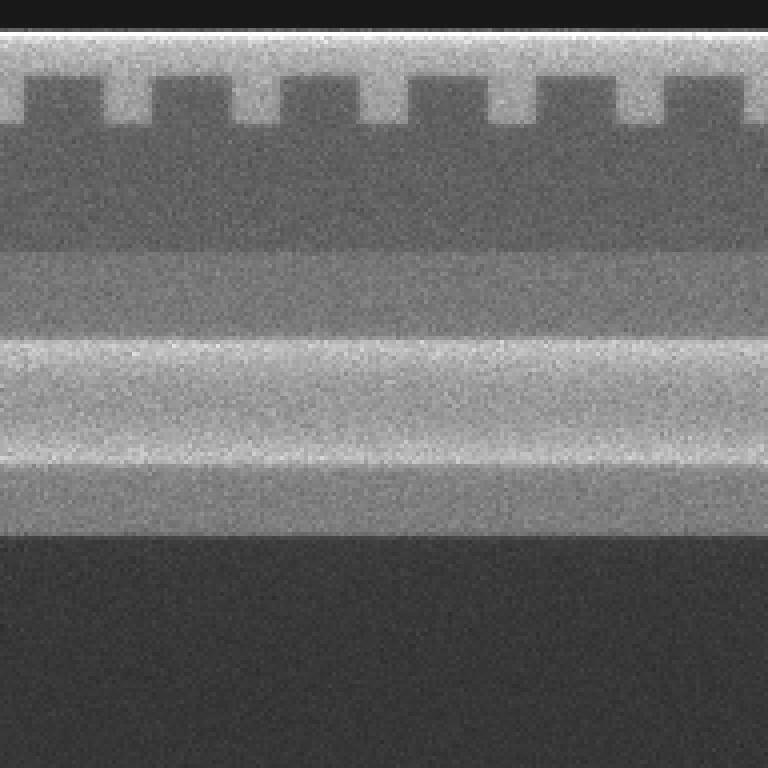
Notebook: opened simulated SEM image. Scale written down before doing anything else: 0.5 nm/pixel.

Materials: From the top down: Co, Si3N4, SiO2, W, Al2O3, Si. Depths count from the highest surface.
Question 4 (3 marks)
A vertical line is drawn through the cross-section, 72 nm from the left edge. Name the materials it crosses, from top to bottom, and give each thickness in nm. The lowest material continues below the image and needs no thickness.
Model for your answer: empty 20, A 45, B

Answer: Co 46, Si3N4 64, SiO2 44, W 62, Al2O3 36, Si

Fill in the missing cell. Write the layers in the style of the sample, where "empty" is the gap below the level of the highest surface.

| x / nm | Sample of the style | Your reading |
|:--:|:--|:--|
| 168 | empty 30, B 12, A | Co 22, Si3N4 88, SiO2 44, W 62, Al2O3 36, Si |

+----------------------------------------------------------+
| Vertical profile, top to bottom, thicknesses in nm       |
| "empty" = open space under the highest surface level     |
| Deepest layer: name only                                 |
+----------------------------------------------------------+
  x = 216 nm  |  Co 22, Si3N4 88, SiO2 44, W 62, Al2O3 36, Si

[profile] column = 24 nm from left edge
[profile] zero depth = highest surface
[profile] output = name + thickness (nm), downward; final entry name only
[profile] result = Co 22, Si3N4 88, SiO2 44, W 62, Al2O3 36, Si